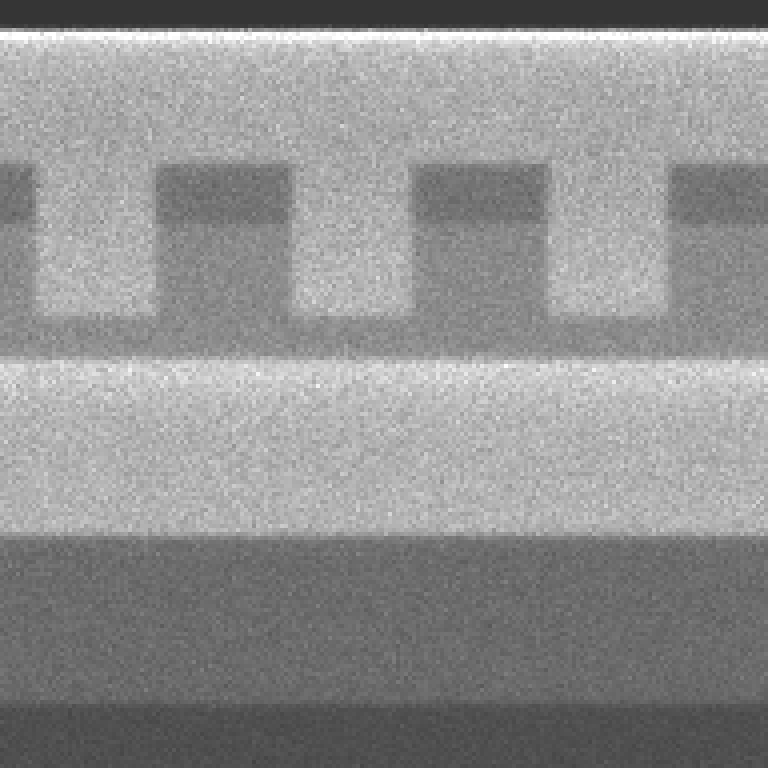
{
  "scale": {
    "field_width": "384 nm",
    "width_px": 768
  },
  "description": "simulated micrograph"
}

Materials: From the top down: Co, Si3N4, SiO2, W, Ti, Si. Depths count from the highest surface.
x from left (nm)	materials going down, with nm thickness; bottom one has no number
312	Co 142, SiO2 22, W 88, Ti 84, Si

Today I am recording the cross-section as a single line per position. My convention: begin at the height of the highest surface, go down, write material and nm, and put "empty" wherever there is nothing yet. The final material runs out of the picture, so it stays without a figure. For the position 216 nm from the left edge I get Co 66, Si3N4 30, SiO2 68, W 88, Ti 84, Si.